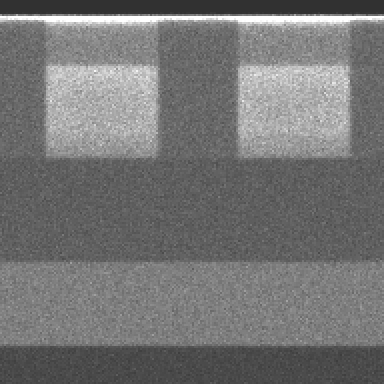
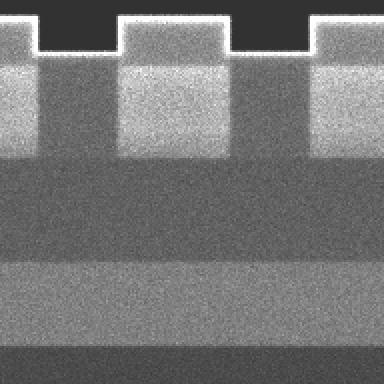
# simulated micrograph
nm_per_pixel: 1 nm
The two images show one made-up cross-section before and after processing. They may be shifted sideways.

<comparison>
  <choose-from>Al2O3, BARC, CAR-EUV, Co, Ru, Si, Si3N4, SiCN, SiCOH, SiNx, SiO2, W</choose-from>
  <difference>Si3N4 removed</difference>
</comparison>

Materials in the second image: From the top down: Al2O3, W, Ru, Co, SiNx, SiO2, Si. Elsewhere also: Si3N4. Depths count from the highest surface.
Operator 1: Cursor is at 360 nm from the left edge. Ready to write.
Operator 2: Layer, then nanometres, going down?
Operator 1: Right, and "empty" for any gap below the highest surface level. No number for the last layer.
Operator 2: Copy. Al2O3 50, W 68, Ru 12, Co 12, SiNx 104, SiO2 84, Si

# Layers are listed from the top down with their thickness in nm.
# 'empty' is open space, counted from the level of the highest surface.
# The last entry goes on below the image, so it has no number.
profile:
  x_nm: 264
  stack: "empty 36, Si3N4 106, SiNx 104, SiO2 84, Si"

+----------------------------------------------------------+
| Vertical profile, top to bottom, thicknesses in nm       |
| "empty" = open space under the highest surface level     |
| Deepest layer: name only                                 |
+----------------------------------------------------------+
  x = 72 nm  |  empty 36, Si3N4 106, SiNx 104, SiO2 84, Si